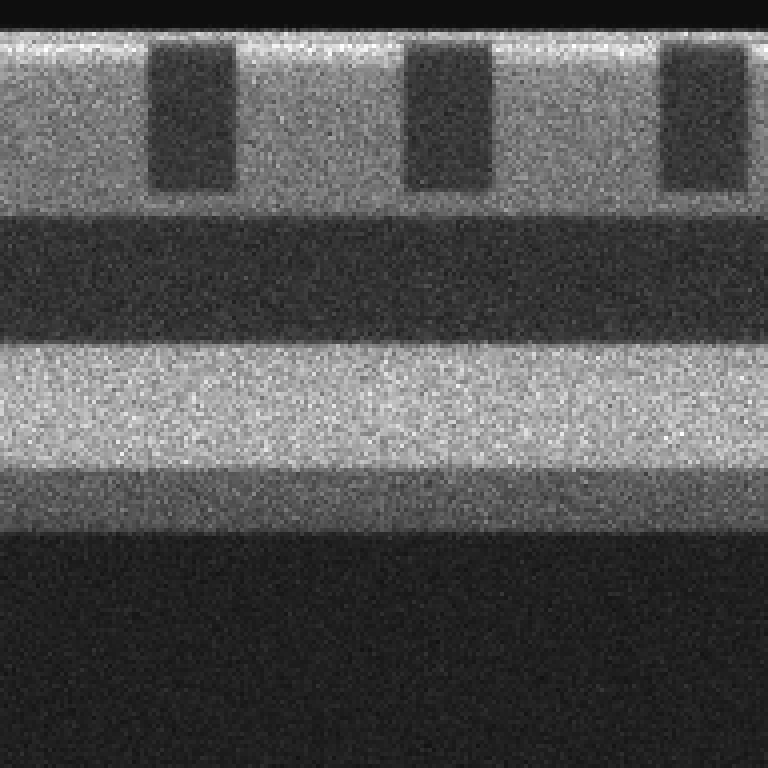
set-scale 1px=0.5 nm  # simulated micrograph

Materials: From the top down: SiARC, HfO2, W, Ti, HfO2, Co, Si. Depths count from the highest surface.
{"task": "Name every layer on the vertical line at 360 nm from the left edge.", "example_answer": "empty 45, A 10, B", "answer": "SiARC 80, W 12, Ti 64, HfO2 62, Co 32, Si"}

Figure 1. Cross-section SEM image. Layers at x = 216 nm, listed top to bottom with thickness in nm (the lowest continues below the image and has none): SiARC 80, W 12, Ti 64, HfO2 62, Co 32, Si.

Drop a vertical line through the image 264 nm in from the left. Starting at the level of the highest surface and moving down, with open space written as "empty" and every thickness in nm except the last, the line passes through SiARC 6, HfO2 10, W 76, Ti 64, HfO2 62, Co 32, Si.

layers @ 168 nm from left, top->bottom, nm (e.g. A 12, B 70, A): SiARC 6, HfO2 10, W 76, Ti 64, HfO2 62, Co 32, Si